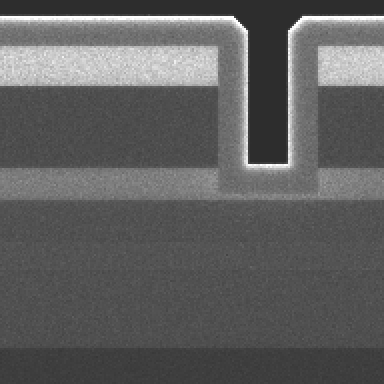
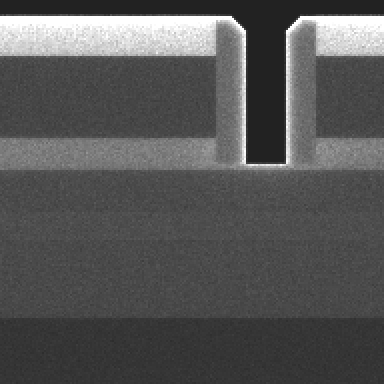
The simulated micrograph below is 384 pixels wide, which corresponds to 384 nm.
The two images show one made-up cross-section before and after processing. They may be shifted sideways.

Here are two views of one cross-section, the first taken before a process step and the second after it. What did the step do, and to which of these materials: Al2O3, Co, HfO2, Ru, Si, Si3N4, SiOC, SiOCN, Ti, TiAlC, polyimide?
It removed Al2O3.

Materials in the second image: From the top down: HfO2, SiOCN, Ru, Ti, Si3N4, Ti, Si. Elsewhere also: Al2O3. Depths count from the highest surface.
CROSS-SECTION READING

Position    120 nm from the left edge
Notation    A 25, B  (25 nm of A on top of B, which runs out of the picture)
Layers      HfO2 40, SiOCN 82, Ru 32, Ti 42, Si3N4 28, Ti 78, Si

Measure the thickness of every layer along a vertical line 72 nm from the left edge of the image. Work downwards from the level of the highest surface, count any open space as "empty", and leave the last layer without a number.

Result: HfO2 40, SiOCN 82, Ru 32, Ti 42, Si3N4 28, Ti 78, Si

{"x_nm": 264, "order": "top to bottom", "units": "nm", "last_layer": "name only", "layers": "empty 148, Ru 6, Ti 42, Si3N4 28, Ti 78, Si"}